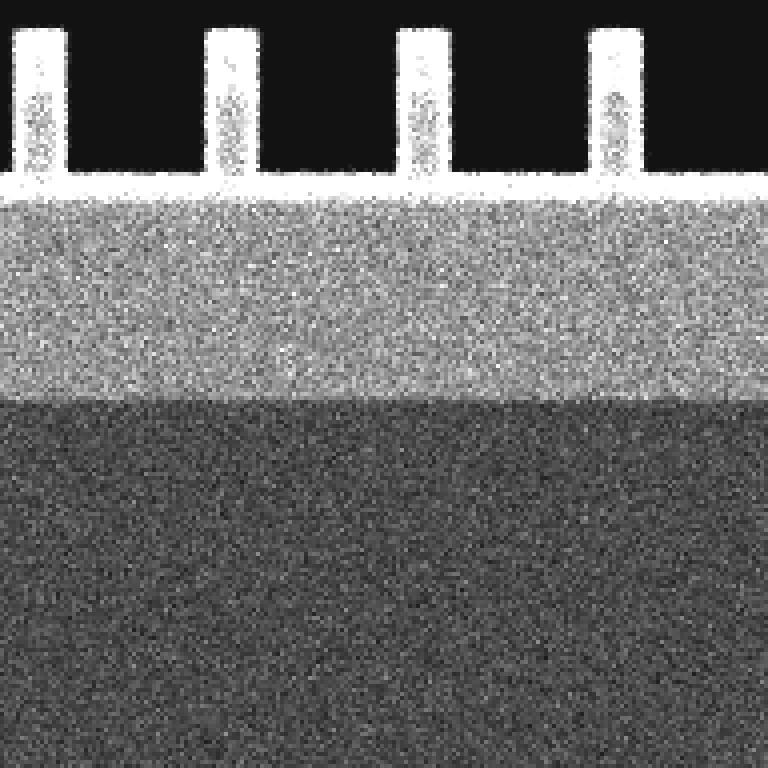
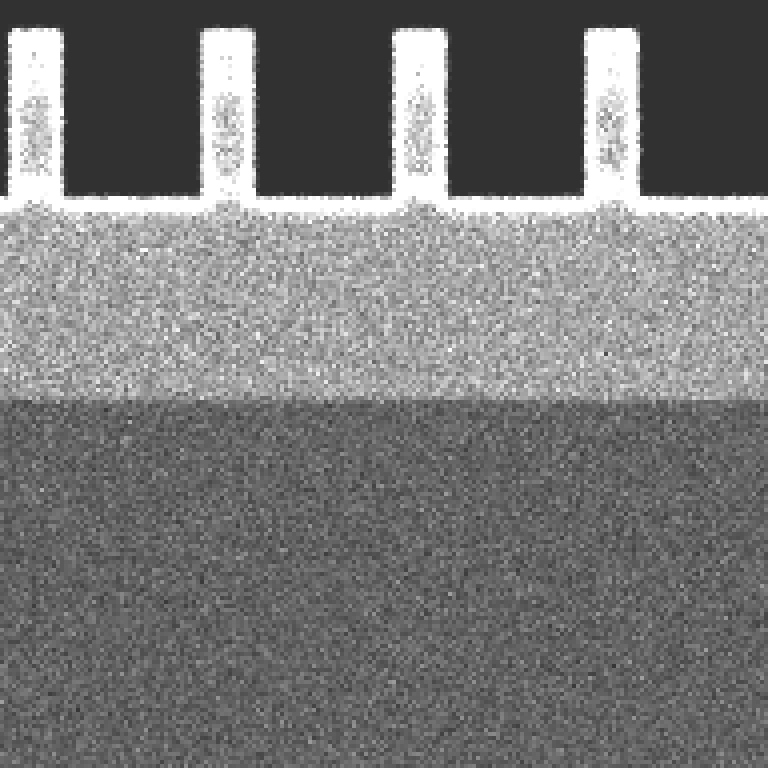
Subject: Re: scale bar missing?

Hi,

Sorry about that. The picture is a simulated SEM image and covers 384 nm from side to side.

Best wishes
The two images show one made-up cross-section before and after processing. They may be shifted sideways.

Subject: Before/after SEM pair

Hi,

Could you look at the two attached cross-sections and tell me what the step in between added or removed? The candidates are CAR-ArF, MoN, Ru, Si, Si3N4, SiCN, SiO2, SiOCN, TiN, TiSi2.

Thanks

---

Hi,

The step removed Ru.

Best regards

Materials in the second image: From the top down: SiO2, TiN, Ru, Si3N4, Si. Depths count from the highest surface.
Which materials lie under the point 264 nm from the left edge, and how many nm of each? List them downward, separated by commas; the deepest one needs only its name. empty 84, Si3N4 100, Si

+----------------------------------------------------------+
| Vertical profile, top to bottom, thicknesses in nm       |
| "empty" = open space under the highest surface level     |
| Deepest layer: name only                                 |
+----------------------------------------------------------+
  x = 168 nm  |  empty 84, Si3N4 100, Si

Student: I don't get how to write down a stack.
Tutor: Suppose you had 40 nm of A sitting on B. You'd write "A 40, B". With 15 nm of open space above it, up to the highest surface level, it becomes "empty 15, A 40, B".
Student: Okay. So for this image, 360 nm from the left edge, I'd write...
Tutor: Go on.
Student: empty 84, Si3N4 100, Si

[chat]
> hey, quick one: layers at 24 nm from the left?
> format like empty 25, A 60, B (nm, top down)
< SiO2 30, TiN 42, Ru 12, Si3N4 100, Si